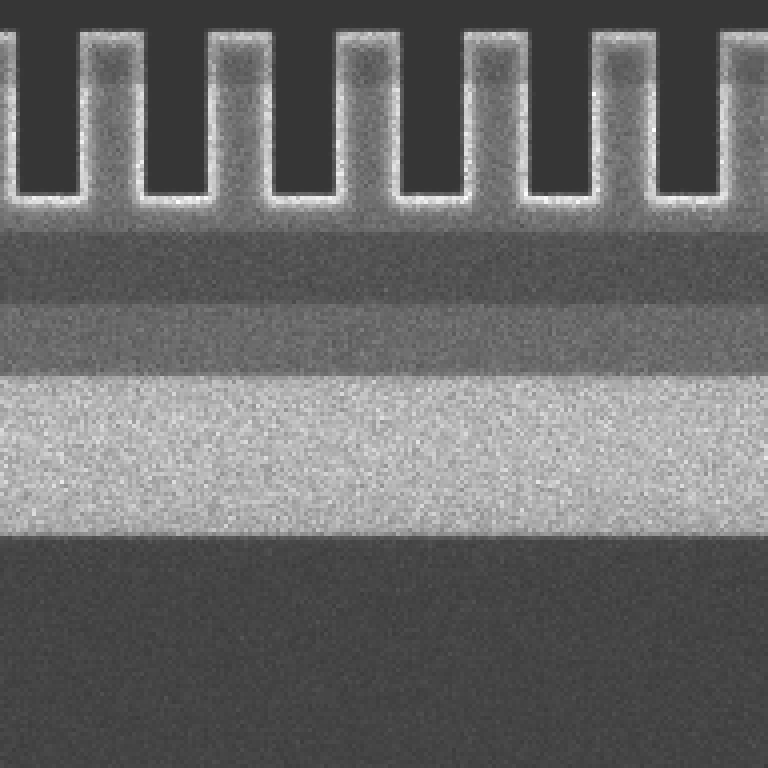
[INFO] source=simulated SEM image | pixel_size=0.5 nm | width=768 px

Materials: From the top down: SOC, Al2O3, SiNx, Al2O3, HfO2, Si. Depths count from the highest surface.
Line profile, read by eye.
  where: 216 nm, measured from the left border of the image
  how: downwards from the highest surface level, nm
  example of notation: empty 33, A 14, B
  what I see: empty 82, Al2O3 18, SiNx 36, Al2O3 36, HfO2 80, Si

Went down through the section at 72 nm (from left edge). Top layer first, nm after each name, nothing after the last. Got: empty 82, Al2O3 18, SiNx 36, Al2O3 36, HfO2 80, Si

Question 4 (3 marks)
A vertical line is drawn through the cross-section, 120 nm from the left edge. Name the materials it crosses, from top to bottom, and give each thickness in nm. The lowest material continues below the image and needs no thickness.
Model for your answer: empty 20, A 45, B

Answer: SOC 26, Al2O3 74, SiNx 36, Al2O3 36, HfO2 80, Si